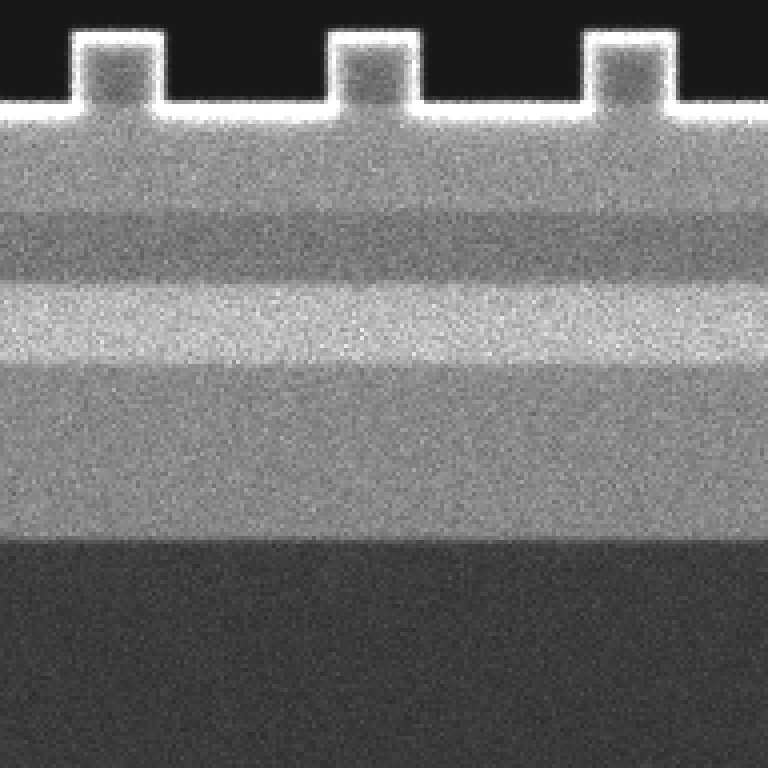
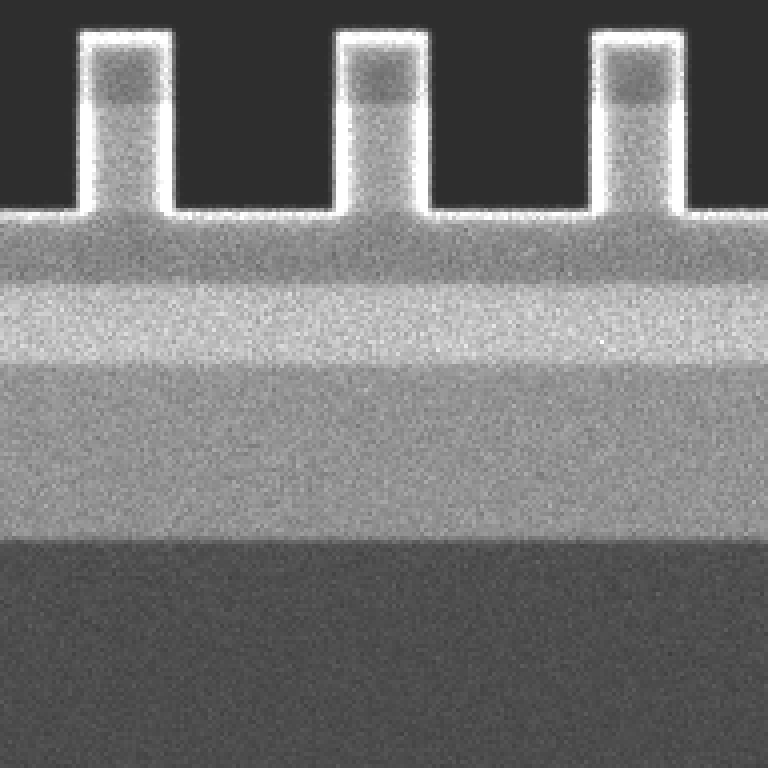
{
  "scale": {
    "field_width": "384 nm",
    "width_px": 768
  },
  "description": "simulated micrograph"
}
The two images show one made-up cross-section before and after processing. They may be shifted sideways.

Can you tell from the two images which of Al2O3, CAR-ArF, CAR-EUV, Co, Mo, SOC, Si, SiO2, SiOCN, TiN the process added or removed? Yes, it removed Al2O3.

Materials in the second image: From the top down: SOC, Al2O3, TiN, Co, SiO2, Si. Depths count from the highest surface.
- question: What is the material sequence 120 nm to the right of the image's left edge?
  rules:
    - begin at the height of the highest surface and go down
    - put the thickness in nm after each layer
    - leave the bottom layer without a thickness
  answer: empty 90, TiN 36, Co 40, SiO2 88, Si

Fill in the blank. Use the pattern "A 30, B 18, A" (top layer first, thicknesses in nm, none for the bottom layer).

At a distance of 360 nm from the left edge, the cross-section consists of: empty 90, TiN 36, Co 40, SiO2 88, Si